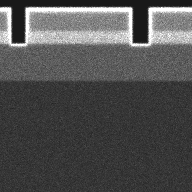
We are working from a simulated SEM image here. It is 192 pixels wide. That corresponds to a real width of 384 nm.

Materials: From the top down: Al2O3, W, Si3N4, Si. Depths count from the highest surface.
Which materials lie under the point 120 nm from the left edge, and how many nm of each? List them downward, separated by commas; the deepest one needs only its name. Al2O3 46, W 26, Si3N4 74, Si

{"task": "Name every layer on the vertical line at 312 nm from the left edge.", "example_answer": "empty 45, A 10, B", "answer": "Al2O3 46, W 26, Si3N4 74, Si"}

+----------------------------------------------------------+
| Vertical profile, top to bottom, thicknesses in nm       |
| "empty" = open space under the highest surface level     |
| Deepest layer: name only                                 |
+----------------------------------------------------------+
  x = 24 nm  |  empty 72, Si3N4 74, Si